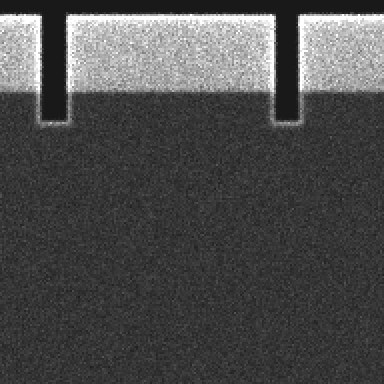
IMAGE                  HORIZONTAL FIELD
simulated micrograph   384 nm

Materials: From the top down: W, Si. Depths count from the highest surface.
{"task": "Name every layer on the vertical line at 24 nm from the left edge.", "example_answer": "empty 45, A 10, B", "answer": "W 76, Si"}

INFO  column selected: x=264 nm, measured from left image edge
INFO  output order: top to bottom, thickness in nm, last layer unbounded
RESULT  W 76, Si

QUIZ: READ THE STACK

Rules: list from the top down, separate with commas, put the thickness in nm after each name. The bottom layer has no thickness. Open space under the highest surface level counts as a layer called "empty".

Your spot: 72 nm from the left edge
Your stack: W 76, Si